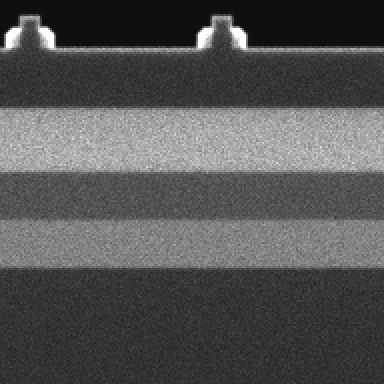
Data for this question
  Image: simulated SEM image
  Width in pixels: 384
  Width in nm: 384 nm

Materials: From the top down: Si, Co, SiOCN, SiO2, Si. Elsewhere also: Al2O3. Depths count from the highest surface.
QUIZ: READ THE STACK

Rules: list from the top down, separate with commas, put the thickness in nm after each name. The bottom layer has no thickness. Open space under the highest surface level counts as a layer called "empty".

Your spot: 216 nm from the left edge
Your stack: Si 92, Co 64, SiOCN 48, SiO2 48, Si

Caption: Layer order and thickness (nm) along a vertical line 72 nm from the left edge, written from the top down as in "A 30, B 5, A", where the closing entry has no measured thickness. empty 32, Si 60, Co 64, SiOCN 48, SiO2 48, Si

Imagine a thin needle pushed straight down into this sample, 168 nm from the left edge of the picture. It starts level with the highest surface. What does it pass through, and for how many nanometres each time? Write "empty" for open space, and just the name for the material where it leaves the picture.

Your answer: empty 32, Si 60, Co 64, SiOCN 48, SiO2 48, Si